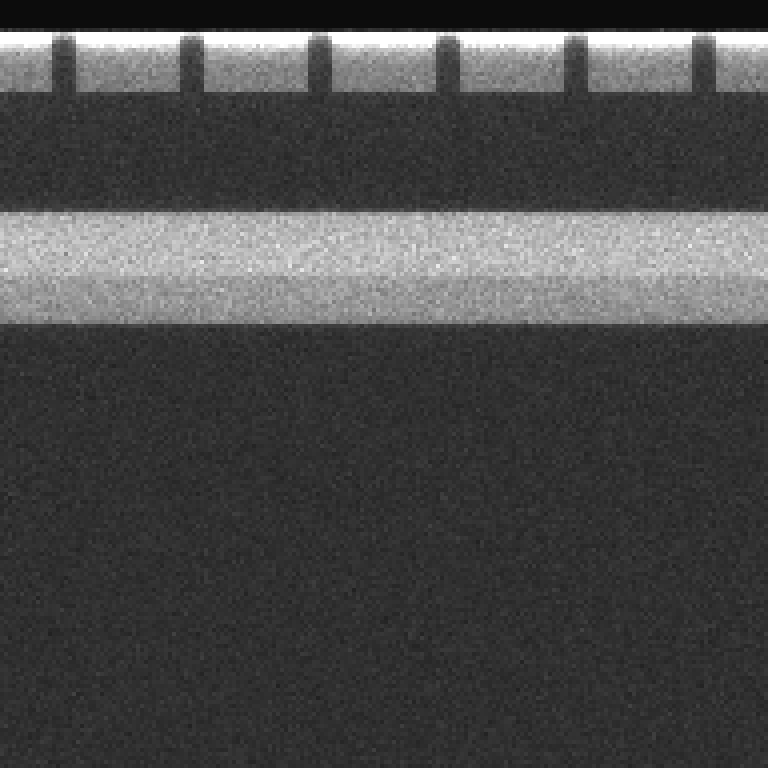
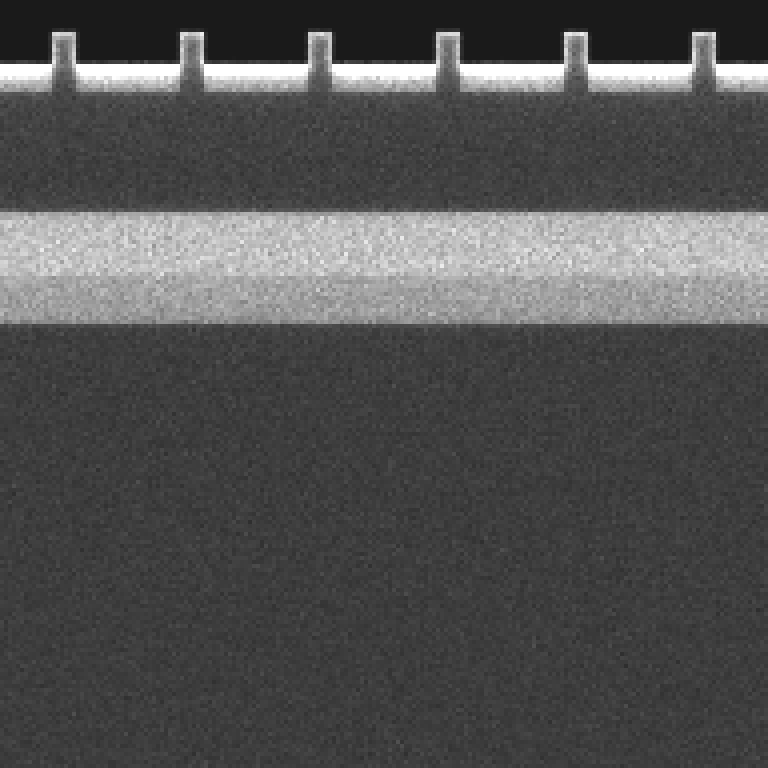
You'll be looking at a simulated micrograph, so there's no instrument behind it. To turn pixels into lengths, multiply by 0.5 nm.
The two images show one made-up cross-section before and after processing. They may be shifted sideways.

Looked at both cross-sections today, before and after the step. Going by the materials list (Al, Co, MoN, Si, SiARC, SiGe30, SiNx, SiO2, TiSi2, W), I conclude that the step removed SiO2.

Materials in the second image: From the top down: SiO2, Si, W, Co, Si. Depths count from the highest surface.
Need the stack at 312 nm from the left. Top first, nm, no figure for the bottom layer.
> empty 16, SiO2 14, Si 60, W 32, Co 24, Si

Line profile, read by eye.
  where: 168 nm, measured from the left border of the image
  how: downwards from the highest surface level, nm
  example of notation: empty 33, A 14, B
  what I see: empty 16, SiO2 14, Si 60, W 32, Co 24, Si